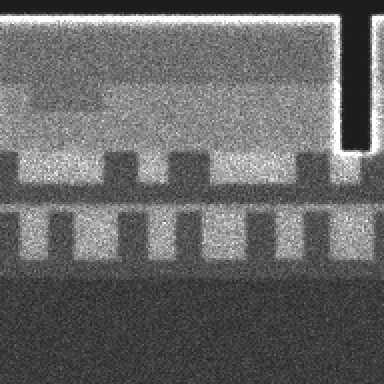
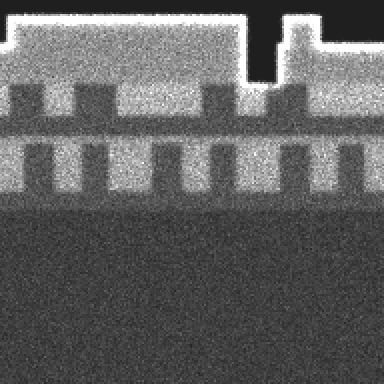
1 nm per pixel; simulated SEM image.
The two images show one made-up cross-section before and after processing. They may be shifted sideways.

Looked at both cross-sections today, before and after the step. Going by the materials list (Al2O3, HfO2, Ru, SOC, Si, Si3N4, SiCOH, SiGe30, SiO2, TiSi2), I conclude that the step removed SOC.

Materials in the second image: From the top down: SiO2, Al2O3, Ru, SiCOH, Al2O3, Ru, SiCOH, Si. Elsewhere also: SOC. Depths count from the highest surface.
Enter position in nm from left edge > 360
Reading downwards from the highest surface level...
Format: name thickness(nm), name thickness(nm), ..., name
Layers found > empty 28, SiO2 30, Al2O3 10, Ru 32, SiCOH 20, Al2O3 8, SiCOH 66, Si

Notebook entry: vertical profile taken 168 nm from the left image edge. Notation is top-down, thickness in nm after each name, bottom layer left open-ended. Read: SiO2 58, Al2O3 10, Ru 32, SiCOH 20, Al2O3 8, SiCOH 66, Si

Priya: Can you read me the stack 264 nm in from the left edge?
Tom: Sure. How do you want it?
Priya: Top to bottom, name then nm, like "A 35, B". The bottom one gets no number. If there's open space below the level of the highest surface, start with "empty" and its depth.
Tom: empty 68, Ru 32, SiCOH 20, Al2O3 8, Ru 48, SiCOH 18, Si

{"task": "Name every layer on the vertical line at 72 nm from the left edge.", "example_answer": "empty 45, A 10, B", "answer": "SiO2 58, Al2O3 10, Ru 32, SiCOH 20, Al2O3 8, Ru 48, SiCOH 18, Si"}